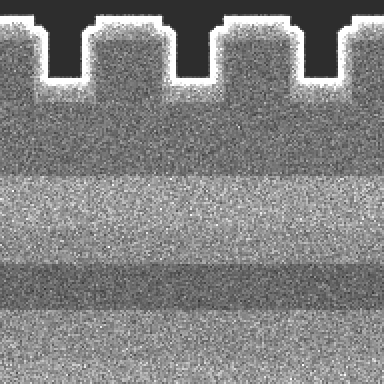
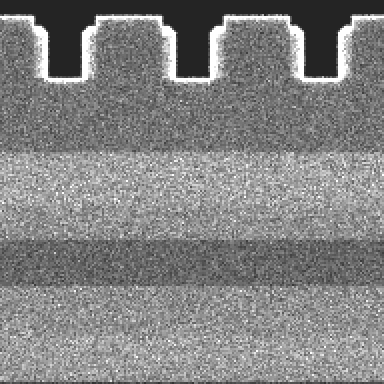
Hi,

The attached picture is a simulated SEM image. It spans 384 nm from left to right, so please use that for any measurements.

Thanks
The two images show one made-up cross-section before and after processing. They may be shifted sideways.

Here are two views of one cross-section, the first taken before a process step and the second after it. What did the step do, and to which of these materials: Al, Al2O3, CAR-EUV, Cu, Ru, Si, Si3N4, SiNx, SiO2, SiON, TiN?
It removed SiO2.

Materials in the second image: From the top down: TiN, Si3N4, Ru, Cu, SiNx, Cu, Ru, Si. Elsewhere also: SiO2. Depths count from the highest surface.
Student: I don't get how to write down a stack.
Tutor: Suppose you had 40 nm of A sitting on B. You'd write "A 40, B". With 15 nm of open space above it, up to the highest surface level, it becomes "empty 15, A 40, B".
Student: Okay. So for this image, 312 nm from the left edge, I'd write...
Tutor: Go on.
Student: empty 62, Si3N4 74, Ru 54, Cu 34, SiNx 46, Cu 50, Ru 46, Si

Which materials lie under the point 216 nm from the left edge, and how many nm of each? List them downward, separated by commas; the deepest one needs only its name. empty 10, SiO2 52, Si3N4 74, Ru 54, Cu 34, SiNx 46, Cu 50, Ru 46, Si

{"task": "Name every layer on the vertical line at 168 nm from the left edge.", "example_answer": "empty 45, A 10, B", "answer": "empty 10, SiO2 52, Si3N4 74, Ru 54, Cu 34, SiNx 46, Cu 50, Ru 46, Si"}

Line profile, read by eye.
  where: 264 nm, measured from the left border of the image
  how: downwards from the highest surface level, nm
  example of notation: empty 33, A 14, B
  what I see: TiN 62, Si3N4 74, Ru 54, Cu 34, SiNx 46, Cu 50, Ru 46, Si